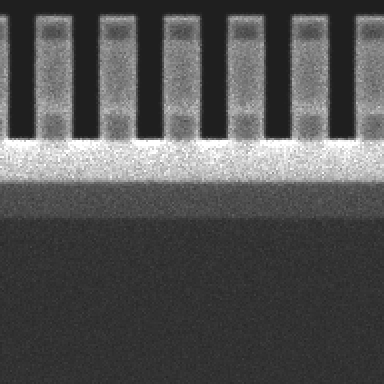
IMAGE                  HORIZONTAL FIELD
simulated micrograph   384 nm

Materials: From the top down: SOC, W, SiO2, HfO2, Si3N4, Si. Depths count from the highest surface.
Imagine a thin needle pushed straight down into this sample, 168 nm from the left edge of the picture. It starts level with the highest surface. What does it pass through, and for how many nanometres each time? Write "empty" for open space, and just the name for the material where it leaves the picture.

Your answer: SOC 24, W 74, SiO2 26, HfO2 42, Si3N4 36, Si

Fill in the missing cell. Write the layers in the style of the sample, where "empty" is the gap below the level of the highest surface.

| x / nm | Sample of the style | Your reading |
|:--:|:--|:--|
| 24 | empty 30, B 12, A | empty 124, HfO2 42, Si3N4 36, Si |